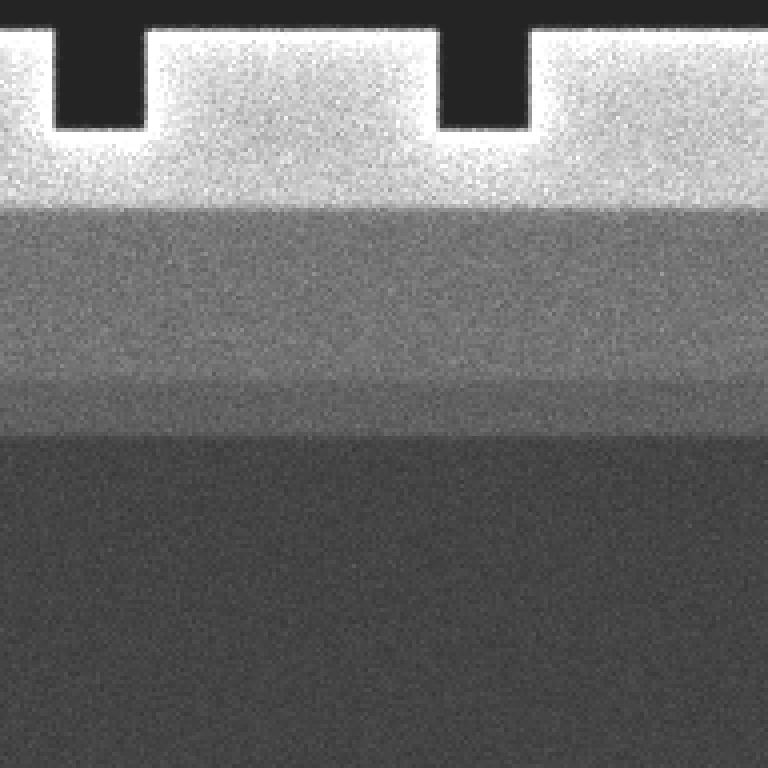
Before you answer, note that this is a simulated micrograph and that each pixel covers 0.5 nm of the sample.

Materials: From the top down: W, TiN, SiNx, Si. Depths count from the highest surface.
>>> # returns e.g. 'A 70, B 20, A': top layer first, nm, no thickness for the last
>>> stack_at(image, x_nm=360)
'W 88, TiN 86, SiNx 28, Si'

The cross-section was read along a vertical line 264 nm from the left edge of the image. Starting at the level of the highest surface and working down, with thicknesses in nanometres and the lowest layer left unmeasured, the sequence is empty 50, W 38, TiN 86, SiNx 28, Si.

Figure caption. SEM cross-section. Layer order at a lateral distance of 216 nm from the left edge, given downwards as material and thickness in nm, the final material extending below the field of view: W 88, TiN 86, SiNx 28, Si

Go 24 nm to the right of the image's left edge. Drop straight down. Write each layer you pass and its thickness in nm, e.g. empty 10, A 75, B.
W 88, TiN 86, SiNx 28, Si